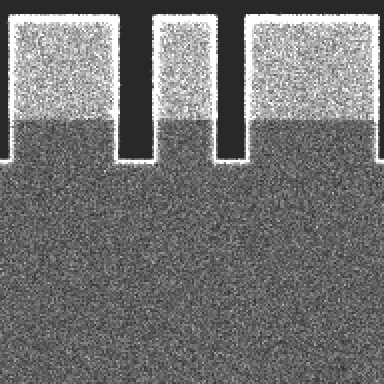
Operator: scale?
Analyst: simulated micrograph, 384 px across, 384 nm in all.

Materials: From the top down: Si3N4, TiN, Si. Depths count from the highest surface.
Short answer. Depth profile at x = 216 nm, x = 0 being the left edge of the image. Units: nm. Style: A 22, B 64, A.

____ empty 144, Si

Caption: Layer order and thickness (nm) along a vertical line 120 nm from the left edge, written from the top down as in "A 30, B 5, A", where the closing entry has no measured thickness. empty 144, Si